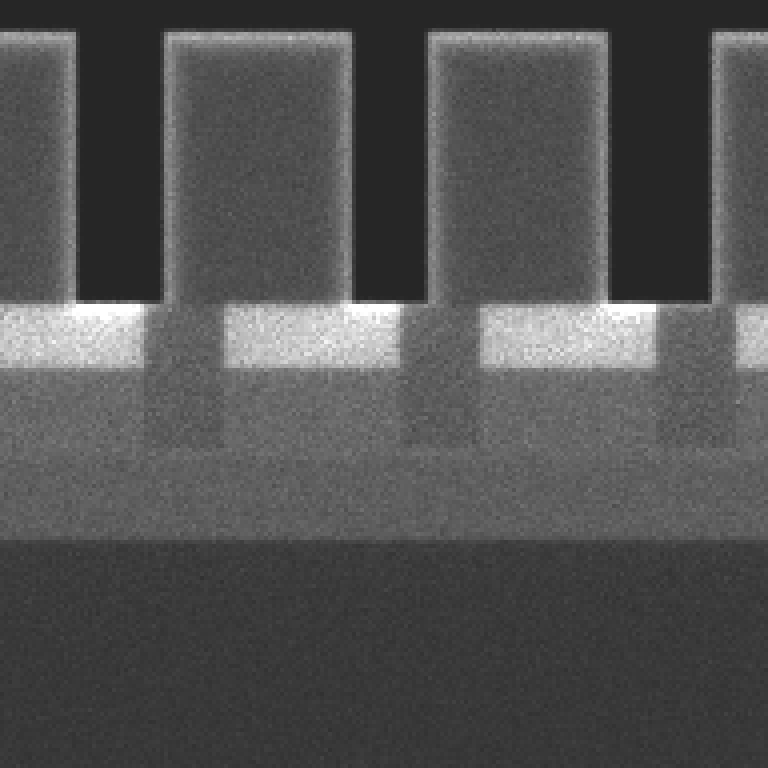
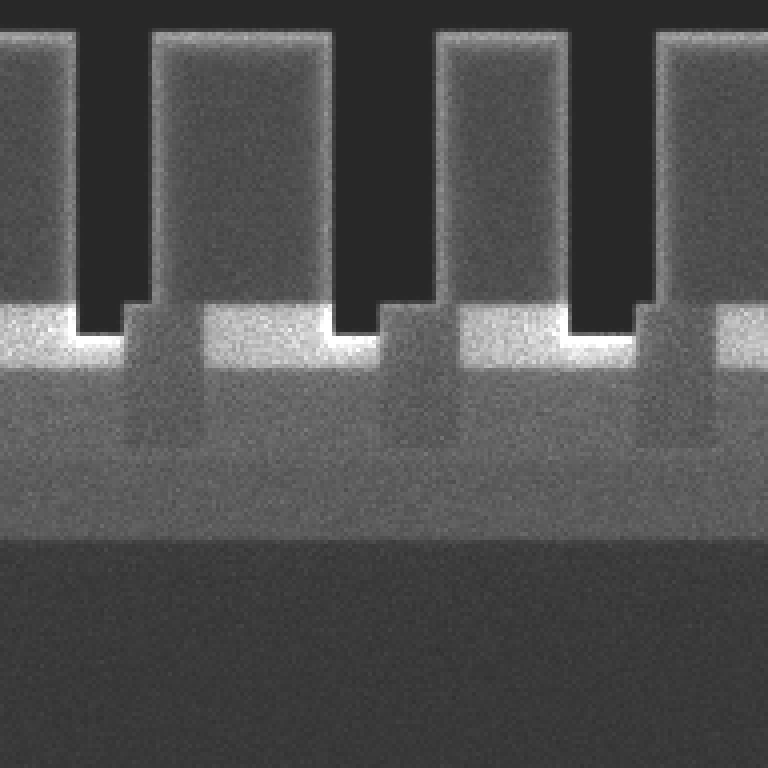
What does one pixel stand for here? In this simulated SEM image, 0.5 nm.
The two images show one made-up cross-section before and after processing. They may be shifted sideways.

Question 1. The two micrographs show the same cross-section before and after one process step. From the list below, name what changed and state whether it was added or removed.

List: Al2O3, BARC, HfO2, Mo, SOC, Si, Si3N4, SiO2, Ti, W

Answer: HfO2, removed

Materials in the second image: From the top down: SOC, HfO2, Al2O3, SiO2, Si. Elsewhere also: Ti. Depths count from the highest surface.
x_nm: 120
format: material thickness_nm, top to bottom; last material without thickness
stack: SOC 136, HfO2 32, Al2O3 46, SiO2 40, Si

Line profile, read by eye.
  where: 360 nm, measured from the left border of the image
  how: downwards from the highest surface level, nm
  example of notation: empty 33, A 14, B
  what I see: SOC 136, HfO2 32, Al2O3 46, SiO2 40, Si